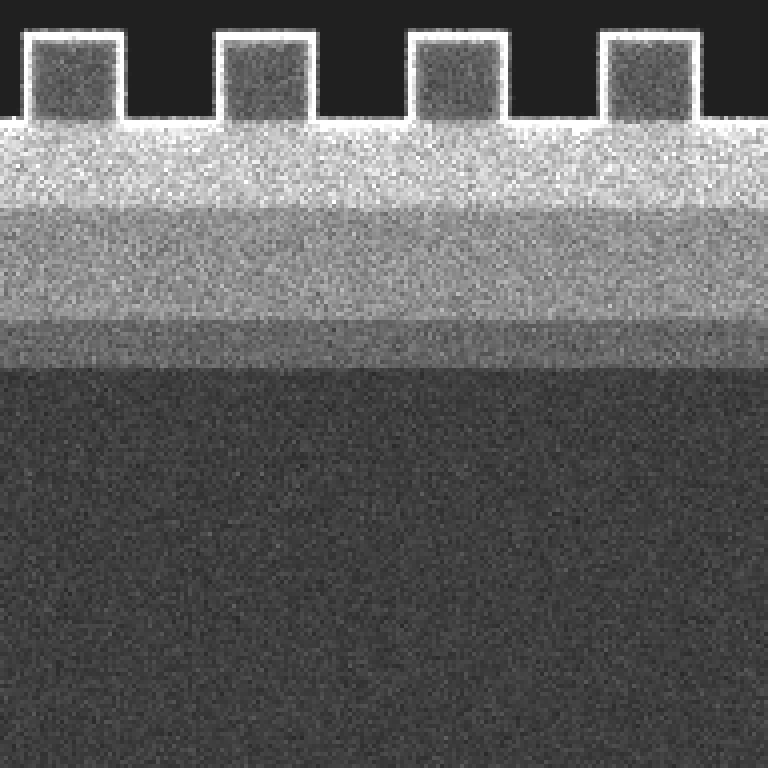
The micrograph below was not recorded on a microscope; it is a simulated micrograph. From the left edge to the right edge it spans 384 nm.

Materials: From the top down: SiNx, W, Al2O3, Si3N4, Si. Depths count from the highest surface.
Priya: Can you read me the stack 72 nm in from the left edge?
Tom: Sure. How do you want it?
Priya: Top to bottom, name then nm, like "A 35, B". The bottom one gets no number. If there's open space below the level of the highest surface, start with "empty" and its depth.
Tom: empty 44, W 44, Al2O3 56, Si3N4 24, Si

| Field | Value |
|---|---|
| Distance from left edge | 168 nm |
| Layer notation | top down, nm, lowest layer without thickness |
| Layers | empty 44, W 44, Al2O3 56, Si3N4 24, Si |